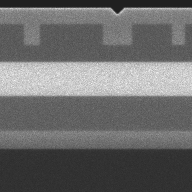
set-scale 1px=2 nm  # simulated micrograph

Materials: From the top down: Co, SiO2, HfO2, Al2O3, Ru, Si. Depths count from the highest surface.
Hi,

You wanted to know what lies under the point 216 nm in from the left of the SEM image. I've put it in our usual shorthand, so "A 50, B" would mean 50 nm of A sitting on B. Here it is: Co 74, SiO2 34, HfO2 68, Al2O3 70, Ru 36, Si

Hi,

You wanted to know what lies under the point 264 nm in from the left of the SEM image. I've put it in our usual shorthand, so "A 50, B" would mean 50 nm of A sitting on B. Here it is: Co 32, SiO2 76, HfO2 68, Al2O3 70, Ru 36, Si